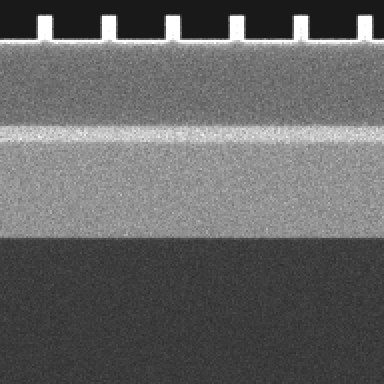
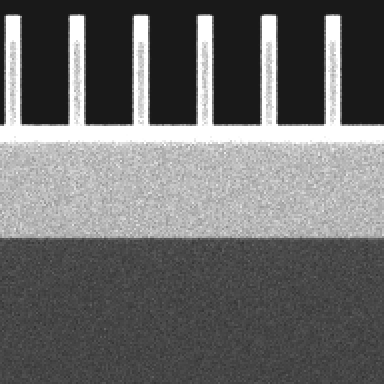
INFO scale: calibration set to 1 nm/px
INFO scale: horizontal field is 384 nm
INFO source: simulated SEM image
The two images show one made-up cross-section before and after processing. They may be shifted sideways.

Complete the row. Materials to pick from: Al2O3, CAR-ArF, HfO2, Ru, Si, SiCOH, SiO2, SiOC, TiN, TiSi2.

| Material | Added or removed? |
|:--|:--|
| TiN | removed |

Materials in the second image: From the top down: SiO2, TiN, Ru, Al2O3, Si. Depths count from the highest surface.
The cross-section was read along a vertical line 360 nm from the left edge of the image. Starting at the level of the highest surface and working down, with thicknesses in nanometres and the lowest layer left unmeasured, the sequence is empty 110, Ru 16, Al2O3 96, Si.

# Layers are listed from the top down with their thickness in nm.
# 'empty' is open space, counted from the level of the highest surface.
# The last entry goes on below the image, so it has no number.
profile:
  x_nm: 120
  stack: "empty 110, Ru 16, Al2O3 96, Si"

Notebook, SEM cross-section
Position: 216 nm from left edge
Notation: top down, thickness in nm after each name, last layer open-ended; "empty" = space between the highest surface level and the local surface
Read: empty 110, Ru 16, Al2O3 96, Si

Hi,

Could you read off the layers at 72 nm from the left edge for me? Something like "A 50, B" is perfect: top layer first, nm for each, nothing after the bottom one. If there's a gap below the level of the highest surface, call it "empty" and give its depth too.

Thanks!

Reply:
SiO2 24, TiN 86, Ru 16, Al2O3 96, Si